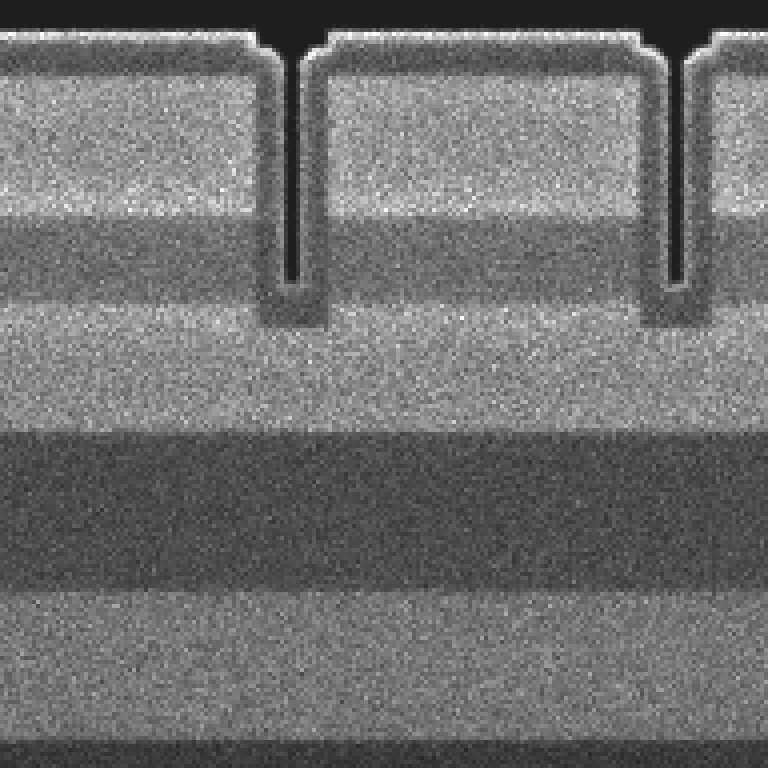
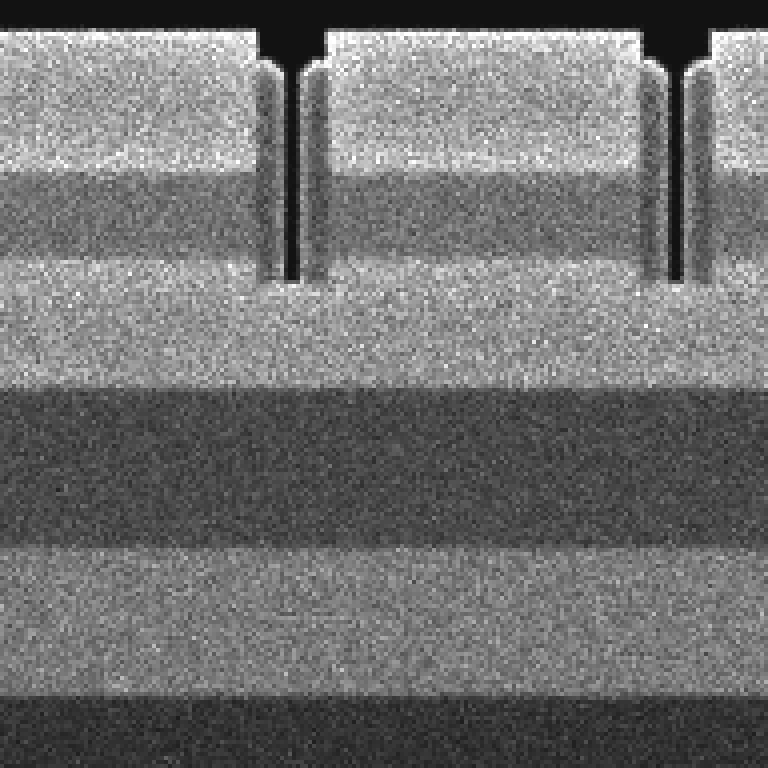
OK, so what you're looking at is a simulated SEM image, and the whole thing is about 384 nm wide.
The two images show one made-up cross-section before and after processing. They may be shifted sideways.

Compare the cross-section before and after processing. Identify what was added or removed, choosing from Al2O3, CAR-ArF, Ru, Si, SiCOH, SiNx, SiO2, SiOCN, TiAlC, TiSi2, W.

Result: SiNx removed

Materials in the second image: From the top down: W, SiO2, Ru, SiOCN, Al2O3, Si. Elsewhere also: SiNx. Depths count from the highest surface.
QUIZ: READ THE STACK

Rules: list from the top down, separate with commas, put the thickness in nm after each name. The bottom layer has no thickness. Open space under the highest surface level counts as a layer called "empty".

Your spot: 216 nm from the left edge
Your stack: W 70, SiO2 44, Ru 64, SiOCN 80, Al2O3 74, Si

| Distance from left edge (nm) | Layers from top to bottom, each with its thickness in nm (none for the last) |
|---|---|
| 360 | W 70, SiO2 44, Ru 64, SiOCN 80, Al2O3 74, Si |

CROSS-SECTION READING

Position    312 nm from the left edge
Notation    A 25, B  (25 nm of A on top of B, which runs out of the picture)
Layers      W 70, SiO2 44, Ru 64, SiOCN 80, Al2O3 74, Si